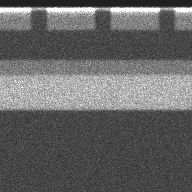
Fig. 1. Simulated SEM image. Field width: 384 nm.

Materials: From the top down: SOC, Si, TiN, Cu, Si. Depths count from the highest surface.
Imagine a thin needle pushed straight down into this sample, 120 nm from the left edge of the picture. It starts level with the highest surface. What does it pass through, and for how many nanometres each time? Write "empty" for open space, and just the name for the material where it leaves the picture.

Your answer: SOC 44, Si 60, TiN 30, Cu 70, Si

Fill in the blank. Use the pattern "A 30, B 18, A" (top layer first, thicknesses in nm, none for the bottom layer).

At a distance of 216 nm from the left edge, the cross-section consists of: Si 104, TiN 30, Cu 70, Si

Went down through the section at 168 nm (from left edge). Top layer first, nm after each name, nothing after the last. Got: SOC 44, Si 60, TiN 30, Cu 70, Si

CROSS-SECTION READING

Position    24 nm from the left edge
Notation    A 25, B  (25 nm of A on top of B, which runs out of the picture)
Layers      SOC 44, Si 60, TiN 30, Cu 70, Si